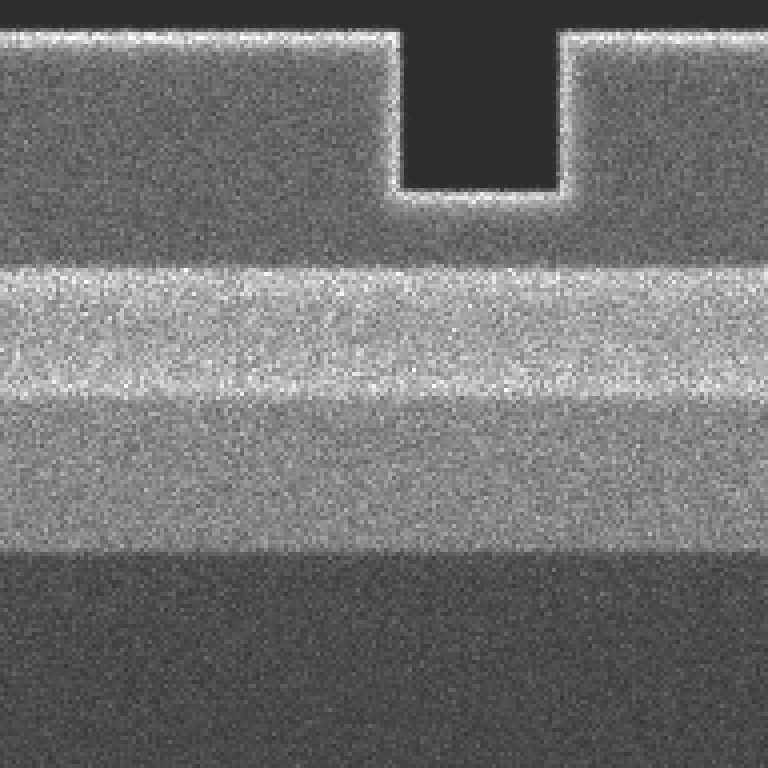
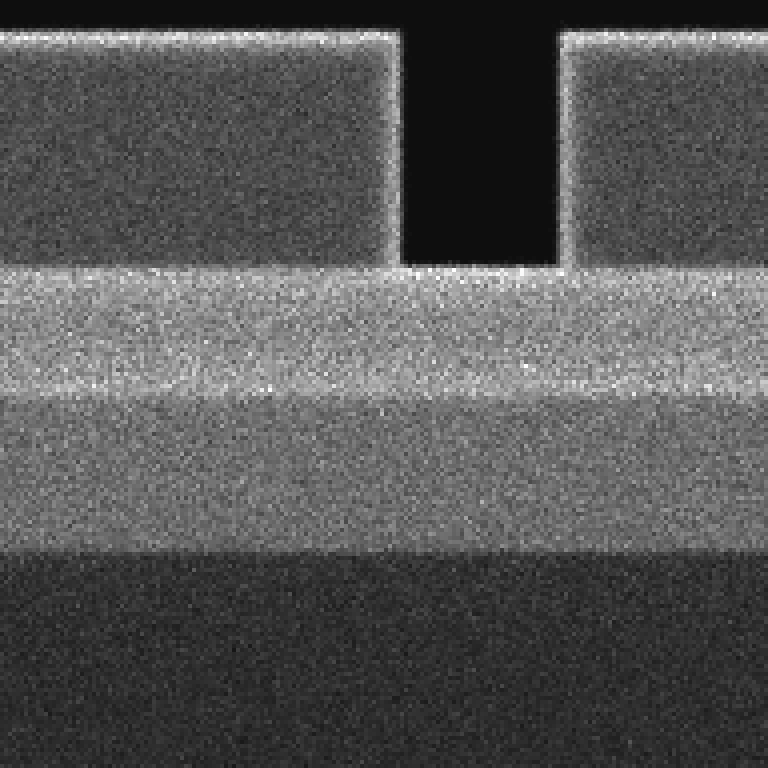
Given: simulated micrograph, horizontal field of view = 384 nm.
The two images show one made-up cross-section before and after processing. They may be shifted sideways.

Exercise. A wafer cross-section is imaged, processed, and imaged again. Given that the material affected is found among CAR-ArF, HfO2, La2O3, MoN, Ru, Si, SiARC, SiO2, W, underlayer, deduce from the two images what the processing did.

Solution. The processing removed underlayer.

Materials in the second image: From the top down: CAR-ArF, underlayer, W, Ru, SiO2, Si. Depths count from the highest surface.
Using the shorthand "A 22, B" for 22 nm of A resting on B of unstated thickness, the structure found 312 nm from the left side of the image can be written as CAR-ArF 80, underlayer 38, W 48, Ru 16, SiO2 78, Si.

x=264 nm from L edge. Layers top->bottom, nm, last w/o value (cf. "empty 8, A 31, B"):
empty 118, W 48, Ru 16, SiO2 78, Si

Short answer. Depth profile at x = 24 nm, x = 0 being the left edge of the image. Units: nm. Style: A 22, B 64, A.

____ CAR-ArF 80, underlayer 38, W 48, Ru 16, SiO2 78, Si